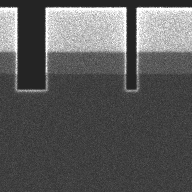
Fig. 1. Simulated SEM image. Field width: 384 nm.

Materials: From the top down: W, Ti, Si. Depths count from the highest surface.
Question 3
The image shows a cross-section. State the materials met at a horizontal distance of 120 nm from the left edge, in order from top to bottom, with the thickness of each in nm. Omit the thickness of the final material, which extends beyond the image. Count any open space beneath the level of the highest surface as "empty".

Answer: W 88, Ti 44, Si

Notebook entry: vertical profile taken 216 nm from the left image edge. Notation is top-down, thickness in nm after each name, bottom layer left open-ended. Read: W 88, Ti 44, Si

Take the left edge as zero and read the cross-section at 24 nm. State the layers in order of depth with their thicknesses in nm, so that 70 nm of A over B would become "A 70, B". W 88, Ti 44, Si